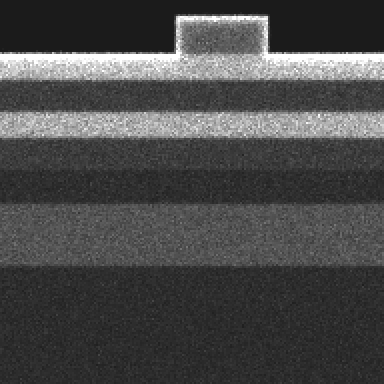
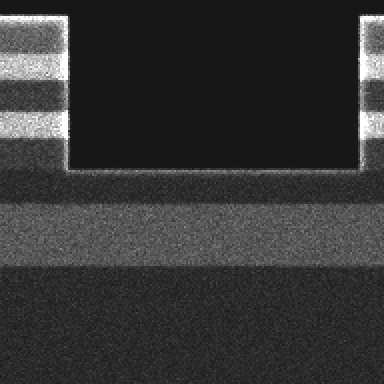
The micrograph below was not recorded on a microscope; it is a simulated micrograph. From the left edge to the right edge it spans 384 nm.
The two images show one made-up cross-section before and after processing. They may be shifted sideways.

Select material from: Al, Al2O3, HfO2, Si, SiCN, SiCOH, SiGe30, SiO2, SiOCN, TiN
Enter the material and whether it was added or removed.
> HfO2 and SiOCN / removed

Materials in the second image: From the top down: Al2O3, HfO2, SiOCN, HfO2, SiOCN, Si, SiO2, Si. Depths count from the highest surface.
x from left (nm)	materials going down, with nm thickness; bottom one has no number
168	empty 154, Si 34, SiO2 62, Si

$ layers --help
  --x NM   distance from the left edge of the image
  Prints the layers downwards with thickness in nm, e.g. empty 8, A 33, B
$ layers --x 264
empty 154, Si 34, SiO2 62, Si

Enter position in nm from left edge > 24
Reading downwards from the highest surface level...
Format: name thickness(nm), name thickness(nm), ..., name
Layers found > Al2O3 38, HfO2 26, SiOCN 32, HfO2 26, SiOCN 32, Si 34, SiO2 62, Si